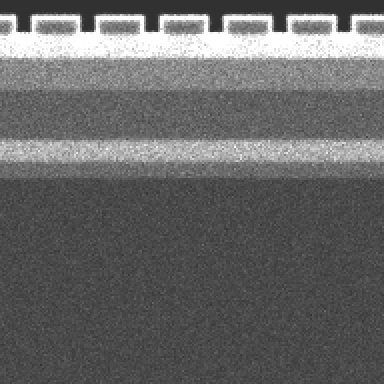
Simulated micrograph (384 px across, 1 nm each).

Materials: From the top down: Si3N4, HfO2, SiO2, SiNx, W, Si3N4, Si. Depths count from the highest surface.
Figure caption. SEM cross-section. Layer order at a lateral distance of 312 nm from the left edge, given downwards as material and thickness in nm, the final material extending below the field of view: Si3N4 18, HfO2 24, SiO2 32, SiNx 50, W 22, Si3N4 16, Si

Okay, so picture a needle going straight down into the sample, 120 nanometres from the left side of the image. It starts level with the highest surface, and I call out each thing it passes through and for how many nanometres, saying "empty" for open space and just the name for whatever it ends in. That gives Si3N4 18, HfO2 24, SiO2 32, SiNx 50, W 22, Si3N4 16, Si